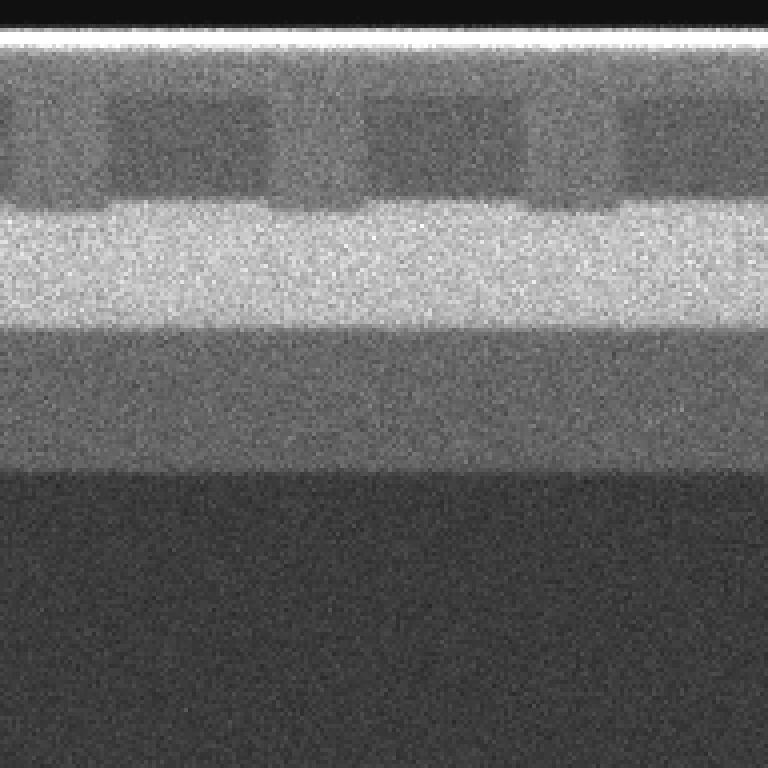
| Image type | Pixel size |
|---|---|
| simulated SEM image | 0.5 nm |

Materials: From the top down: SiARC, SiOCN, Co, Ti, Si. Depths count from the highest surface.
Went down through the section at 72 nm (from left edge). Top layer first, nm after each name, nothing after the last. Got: SiARC 32, SiOCN 52, Co 64, Ti 72, Si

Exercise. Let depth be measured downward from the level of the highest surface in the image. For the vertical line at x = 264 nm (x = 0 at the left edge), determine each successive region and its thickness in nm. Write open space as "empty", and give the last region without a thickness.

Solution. SiARC 90, Co 58, Ti 72, Si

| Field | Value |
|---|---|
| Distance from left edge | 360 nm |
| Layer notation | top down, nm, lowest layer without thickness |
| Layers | SiARC 32, SiOCN 52, Co 64, Ti 72, Si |